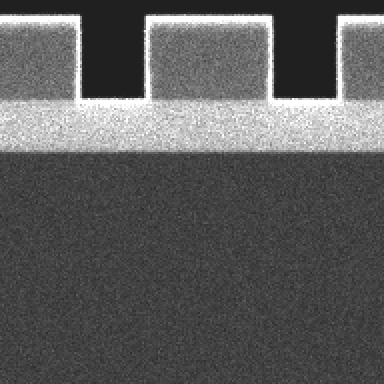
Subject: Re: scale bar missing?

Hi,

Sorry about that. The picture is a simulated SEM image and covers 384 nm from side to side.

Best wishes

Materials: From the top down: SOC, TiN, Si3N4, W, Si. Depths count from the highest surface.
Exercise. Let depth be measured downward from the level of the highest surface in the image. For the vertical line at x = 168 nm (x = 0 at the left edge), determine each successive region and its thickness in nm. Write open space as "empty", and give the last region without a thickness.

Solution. SOC 12, TiN 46, Si3N4 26, W 52, Si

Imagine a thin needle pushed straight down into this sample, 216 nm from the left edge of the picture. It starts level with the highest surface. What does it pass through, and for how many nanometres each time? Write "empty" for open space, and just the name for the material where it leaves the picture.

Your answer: SOC 12, TiN 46, Si3N4 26, W 52, Si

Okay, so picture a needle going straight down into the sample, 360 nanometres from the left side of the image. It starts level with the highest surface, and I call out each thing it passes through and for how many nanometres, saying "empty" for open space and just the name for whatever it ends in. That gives SOC 12, TiN 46, Si3N4 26, W 52, Si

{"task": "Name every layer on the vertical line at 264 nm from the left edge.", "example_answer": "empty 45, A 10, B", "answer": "SOC 12, TiN 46, Si3N4 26, W 52, Si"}